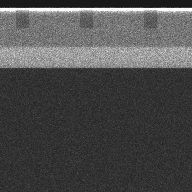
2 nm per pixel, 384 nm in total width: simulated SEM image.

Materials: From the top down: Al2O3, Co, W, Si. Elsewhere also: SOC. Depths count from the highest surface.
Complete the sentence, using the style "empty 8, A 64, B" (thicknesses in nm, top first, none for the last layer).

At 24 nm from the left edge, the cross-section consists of Al2O3 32, Co 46, W 42, Si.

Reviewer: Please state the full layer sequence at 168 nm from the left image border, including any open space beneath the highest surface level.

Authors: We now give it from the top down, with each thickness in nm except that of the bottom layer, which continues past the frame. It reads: SOC 40, Co 38, W 42, Si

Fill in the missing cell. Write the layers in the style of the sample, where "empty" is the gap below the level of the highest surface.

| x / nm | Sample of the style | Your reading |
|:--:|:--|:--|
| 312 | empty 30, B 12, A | SOC 40, Co 38, W 42, Si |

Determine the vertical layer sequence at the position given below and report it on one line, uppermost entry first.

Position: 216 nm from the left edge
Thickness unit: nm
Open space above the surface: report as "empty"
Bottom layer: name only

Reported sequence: Al2O3 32, Co 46, W 42, Si